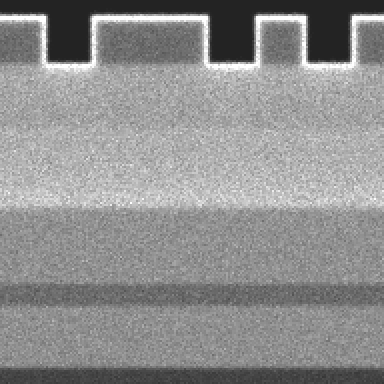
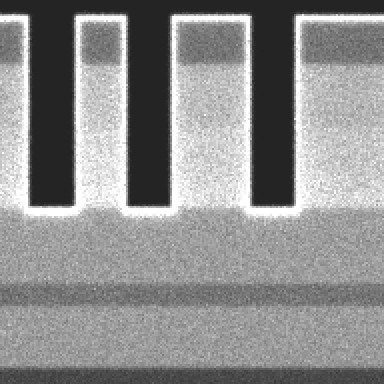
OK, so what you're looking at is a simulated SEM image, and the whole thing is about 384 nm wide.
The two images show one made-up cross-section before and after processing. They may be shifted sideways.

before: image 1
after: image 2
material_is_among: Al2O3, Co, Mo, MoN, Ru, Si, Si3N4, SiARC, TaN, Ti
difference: Co and Ru, removed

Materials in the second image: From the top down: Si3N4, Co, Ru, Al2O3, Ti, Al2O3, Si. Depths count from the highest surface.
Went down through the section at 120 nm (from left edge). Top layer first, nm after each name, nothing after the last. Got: Si3N4 48, Co 64, Ru 80, Al2O3 76, Ti 22, Al2O3 62, Si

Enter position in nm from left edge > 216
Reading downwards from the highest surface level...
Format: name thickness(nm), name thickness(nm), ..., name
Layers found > Si3N4 48, Co 64, Ru 80, Al2O3 76, Ti 22, Al2O3 62, Si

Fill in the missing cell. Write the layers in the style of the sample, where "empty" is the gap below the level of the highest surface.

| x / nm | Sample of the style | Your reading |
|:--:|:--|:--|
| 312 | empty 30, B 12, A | Si3N4 48, Co 64, Ru 80, Al2O3 76, Ti 22, Al2O3 62, Si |